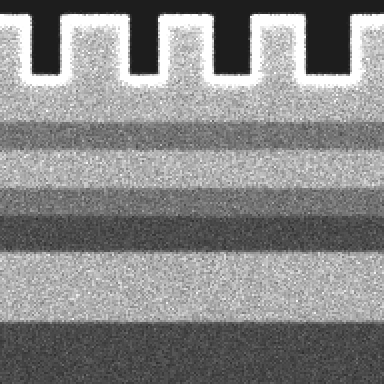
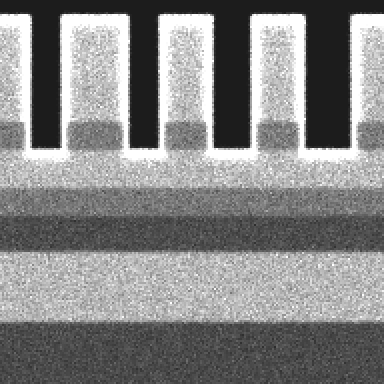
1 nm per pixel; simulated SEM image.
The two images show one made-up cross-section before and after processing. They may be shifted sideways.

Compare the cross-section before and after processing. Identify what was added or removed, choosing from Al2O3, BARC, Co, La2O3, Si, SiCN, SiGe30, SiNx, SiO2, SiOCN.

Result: SiNx and SiO2 removed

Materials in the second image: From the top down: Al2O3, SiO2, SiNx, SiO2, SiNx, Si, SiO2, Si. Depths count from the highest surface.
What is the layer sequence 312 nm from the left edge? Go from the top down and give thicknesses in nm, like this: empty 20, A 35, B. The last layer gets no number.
empty 134, SiO2 38, SiNx 28, Si 36, SiO2 70, Si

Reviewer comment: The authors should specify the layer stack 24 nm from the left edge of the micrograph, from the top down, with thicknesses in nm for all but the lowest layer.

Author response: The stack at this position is Al2O3 60, SiO2 46, SiNx 28, SiO2 38, SiNx 28, Si 36, SiO2 70, Si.